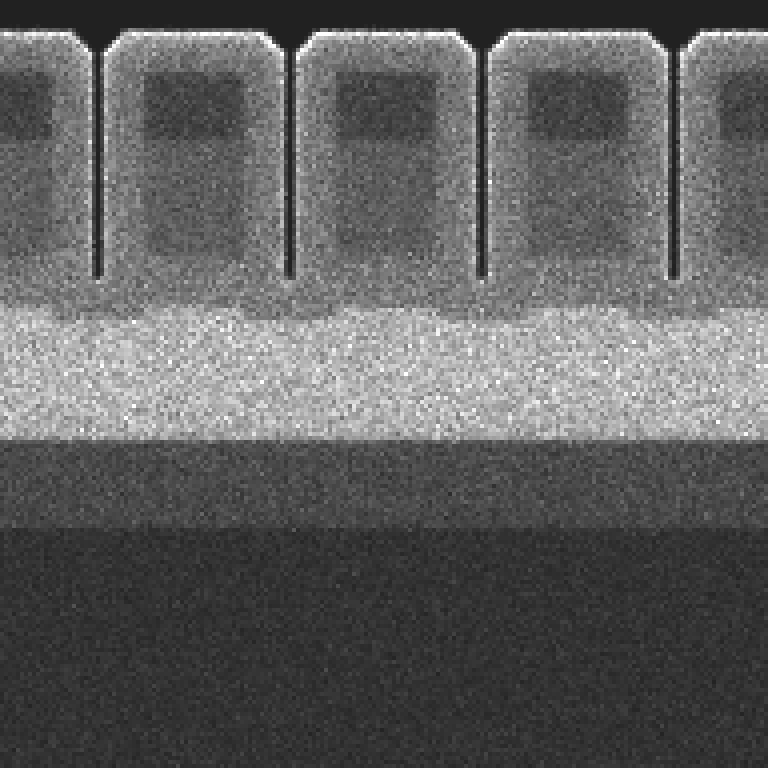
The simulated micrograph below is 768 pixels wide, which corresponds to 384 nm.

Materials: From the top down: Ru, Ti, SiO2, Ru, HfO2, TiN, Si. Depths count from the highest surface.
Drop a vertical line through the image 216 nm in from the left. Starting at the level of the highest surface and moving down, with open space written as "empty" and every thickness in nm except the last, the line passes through Ru 20, Ti 34, SiO2 58, Ru 26, HfO2 66, TiN 44, Si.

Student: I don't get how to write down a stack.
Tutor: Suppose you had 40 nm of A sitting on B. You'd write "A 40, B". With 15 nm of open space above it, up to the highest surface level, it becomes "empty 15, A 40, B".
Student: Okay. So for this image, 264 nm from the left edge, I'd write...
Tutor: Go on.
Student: Ru 20, Ti 34, SiO2 58, Ru 26, HfO2 66, TiN 44, Si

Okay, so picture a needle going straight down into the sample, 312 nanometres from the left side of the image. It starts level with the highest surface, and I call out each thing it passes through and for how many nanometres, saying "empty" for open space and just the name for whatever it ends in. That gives Ru 20, Ti 34, SiO2 58, Ru 26, HfO2 66, TiN 44, Si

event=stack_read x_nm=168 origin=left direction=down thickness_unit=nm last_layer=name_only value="Ru 20, Ti 34, SiO2 58, Ru 26, HfO2 66, TiN 44, Si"